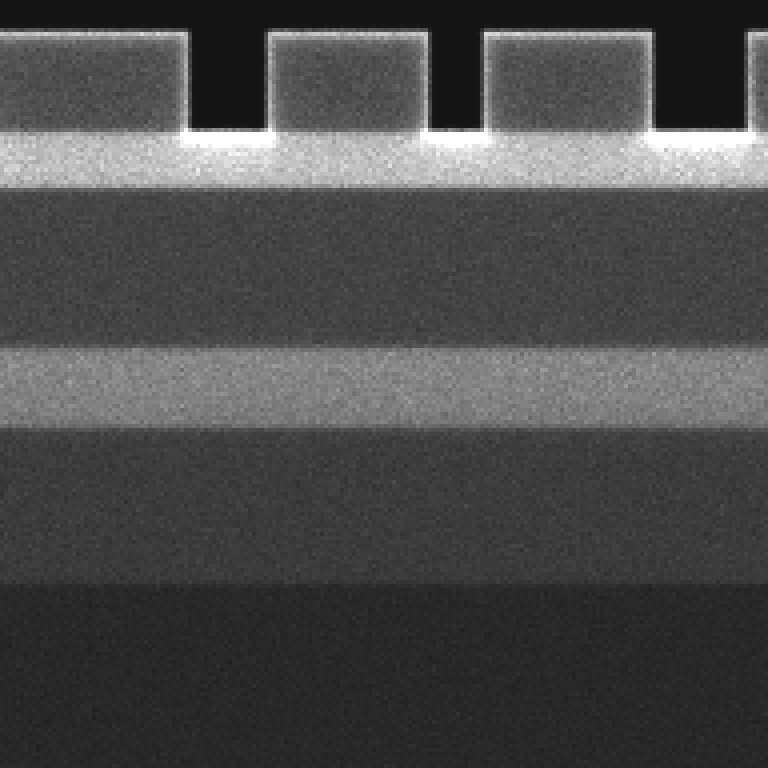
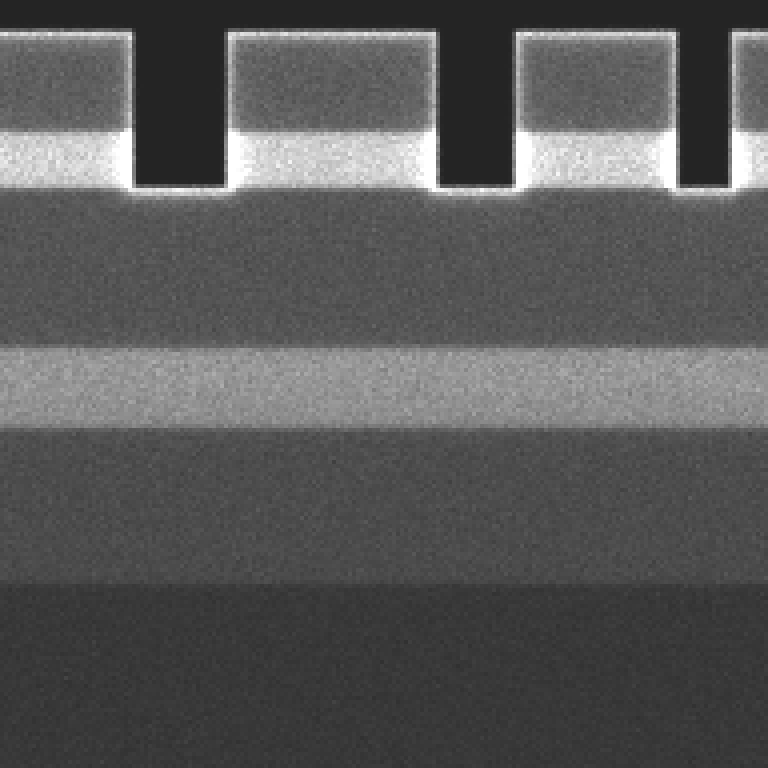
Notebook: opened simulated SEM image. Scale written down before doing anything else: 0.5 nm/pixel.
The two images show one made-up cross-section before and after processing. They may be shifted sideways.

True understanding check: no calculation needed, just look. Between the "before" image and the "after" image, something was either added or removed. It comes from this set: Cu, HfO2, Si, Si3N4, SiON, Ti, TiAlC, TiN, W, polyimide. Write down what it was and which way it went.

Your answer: HfO2 (removed)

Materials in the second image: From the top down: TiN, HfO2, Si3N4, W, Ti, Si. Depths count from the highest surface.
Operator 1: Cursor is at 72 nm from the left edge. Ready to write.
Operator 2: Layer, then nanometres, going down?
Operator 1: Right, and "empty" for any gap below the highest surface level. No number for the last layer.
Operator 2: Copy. empty 78, Si3N4 80, W 40, Ti 78, Si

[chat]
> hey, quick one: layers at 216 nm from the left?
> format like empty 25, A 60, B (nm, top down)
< TiN 50, HfO2 28, Si3N4 80, W 40, Ti 78, Si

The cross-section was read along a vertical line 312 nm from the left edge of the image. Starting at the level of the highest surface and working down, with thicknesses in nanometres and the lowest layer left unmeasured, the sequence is TiN 50, HfO2 28, Si3N4 80, W 40, Ti 78, Si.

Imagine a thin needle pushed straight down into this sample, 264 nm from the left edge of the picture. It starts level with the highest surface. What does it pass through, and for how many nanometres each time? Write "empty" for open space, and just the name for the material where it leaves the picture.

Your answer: TiN 50, HfO2 28, Si3N4 80, W 40, Ti 78, Si